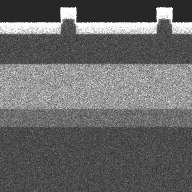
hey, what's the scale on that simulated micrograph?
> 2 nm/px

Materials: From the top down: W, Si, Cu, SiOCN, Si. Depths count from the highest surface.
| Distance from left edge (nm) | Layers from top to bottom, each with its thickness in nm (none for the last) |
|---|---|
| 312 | empty 30, W 22, Si 60, Cu 90, SiOCN 36, Si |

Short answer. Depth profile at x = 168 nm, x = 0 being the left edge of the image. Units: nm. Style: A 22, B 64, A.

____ empty 30, W 22, Si 60, Cu 90, SiOCN 36, Si